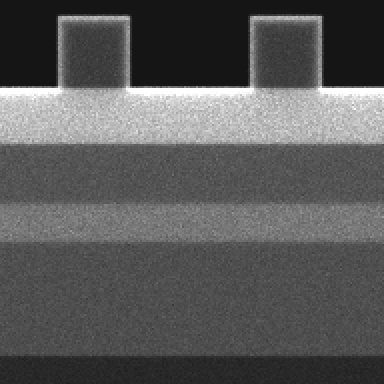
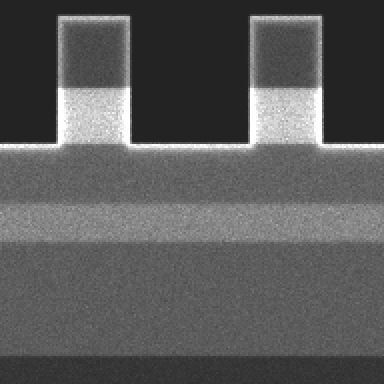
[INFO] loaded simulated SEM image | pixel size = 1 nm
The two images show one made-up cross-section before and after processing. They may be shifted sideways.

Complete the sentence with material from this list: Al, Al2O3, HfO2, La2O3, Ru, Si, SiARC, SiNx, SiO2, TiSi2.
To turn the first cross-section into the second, HfO2 must be removed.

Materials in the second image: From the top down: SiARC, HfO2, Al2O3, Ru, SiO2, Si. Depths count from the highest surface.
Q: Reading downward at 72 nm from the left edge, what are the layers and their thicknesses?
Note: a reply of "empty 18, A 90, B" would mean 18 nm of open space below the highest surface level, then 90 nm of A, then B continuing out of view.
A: SiARC 72, HfO2 56, Al2O3 60, Ru 38, SiO2 114, Si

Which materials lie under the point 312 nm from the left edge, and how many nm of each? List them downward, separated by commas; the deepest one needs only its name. SiARC 72, HfO2 56, Al2O3 60, Ru 38, SiO2 114, Si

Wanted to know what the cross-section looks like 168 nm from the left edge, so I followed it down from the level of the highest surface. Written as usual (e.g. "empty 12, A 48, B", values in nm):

empty 128, Al2O3 60, Ru 38, SiO2 114, Si